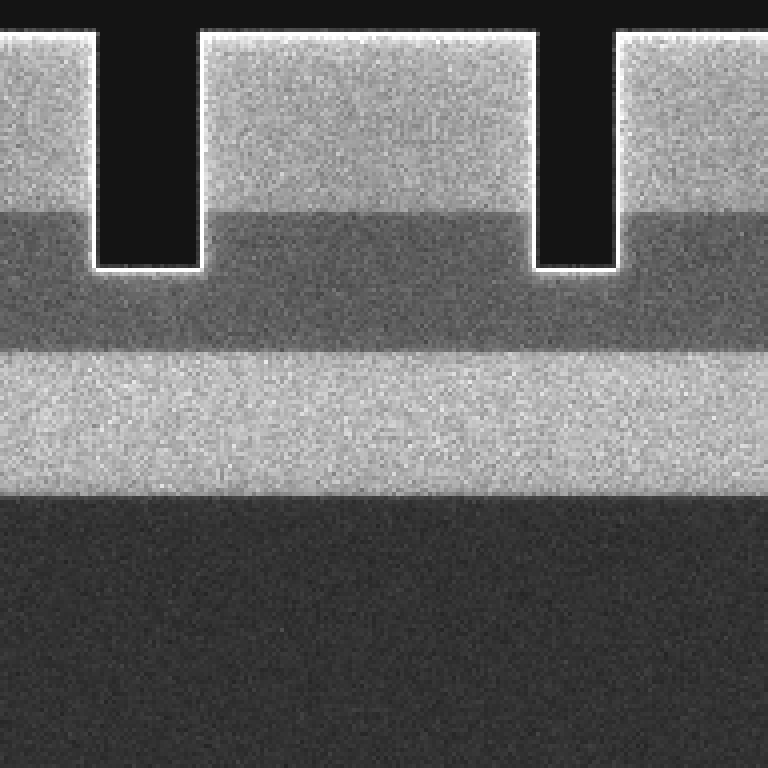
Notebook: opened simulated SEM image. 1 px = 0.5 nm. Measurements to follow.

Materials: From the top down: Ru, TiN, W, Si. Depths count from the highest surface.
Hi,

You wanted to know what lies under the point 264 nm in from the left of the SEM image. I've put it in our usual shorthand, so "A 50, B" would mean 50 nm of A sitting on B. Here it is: Ru 90, TiN 70, W 72, Si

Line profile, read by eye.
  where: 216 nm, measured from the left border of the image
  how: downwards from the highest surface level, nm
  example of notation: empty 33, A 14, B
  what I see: Ru 90, TiN 70, W 72, Si